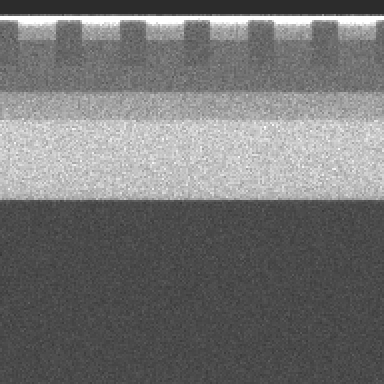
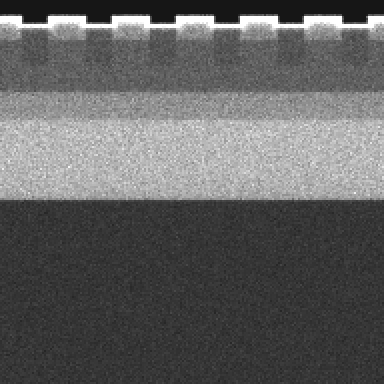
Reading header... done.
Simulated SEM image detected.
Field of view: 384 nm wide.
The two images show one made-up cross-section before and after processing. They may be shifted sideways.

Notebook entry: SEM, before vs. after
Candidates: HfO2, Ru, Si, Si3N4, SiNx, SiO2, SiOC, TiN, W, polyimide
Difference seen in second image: SiNx removed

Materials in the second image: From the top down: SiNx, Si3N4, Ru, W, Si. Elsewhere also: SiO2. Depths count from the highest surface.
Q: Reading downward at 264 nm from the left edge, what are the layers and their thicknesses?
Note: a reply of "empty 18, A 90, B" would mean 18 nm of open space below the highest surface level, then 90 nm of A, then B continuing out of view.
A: SiO2 24, Si3N4 52, Ru 28, W 80, Si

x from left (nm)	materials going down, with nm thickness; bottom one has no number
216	empty 8, SiNx 42, Si3N4 26, Ru 28, W 80, Si